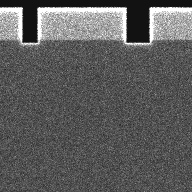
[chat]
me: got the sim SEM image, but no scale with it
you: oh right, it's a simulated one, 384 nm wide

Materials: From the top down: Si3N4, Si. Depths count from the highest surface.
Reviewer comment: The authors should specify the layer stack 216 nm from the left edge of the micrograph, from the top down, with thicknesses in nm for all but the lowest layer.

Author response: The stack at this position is Si3N4 64, Si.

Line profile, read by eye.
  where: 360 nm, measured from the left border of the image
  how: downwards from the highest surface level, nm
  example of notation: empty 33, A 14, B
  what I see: Si3N4 64, Si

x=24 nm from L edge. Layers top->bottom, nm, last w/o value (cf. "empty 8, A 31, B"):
Si3N4 64, Si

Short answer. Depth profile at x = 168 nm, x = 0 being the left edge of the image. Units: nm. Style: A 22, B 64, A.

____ Si3N4 64, Si